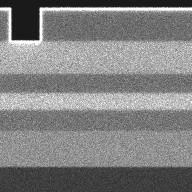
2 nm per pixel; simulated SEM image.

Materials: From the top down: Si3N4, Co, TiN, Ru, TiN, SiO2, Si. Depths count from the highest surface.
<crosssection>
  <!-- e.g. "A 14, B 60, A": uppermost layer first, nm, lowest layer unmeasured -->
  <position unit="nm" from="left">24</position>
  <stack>empty 66, Co 66, TiN 38, Ru 34, TiN 42, SiO2 72, Si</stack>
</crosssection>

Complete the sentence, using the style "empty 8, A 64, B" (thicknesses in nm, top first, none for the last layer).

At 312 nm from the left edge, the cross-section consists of Si3N4 66, Co 66, TiN 38, Ru 34, TiN 42, SiO2 72, Si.